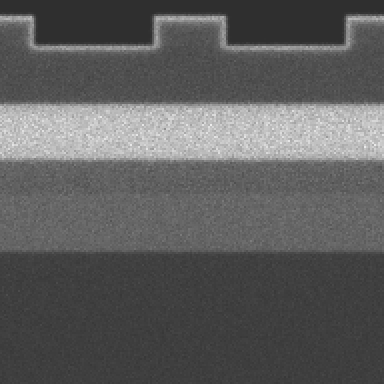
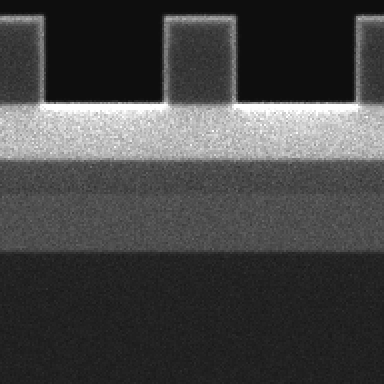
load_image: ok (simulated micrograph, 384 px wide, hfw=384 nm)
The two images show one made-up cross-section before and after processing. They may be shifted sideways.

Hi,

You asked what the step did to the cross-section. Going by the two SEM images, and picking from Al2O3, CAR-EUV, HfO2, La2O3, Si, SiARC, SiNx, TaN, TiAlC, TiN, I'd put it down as SiNx, removed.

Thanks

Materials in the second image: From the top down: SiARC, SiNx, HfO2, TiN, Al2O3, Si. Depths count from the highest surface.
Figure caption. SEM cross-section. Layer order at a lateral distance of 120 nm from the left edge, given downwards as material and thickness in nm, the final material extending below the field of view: empty 88, HfO2 56, TiN 34, Al2O3 58, Si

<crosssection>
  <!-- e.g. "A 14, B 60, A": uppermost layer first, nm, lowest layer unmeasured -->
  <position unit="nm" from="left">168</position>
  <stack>SiARC 30, SiNx 58, HfO2 56, TiN 34, Al2O3 58, Si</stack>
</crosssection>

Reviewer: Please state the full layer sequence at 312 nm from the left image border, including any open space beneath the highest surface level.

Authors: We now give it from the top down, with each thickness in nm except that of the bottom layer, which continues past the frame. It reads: empty 88, HfO2 56, TiN 34, Al2O3 58, Si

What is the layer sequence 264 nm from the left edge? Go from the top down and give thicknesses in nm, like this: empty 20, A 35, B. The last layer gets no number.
empty 88, HfO2 56, TiN 34, Al2O3 58, Si